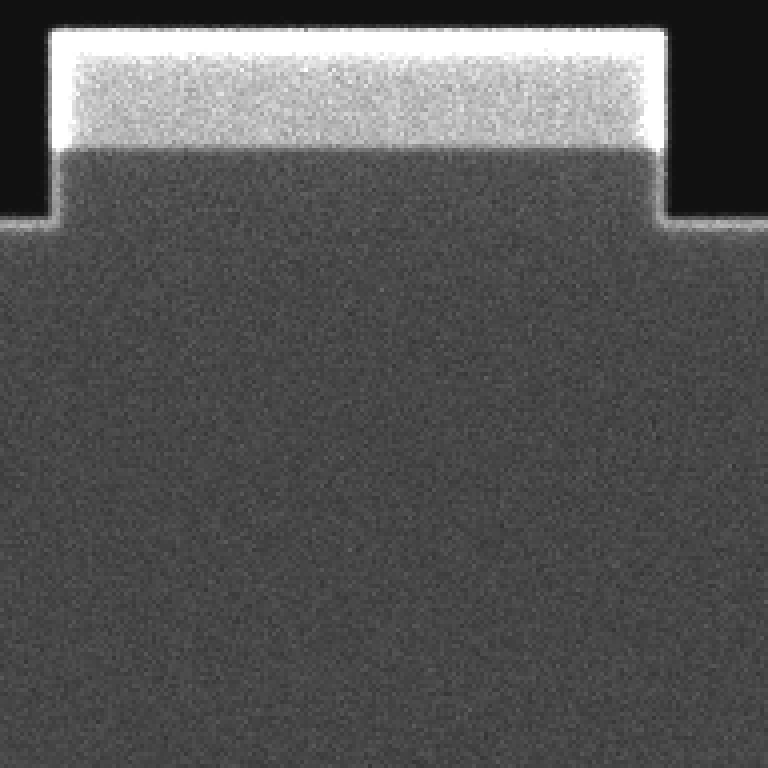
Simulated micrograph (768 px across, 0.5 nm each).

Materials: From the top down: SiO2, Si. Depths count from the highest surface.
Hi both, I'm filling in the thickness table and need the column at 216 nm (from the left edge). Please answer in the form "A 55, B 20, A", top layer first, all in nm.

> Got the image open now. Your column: SiO2 58, Si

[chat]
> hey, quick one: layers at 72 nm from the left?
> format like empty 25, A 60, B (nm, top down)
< SiO2 58, Si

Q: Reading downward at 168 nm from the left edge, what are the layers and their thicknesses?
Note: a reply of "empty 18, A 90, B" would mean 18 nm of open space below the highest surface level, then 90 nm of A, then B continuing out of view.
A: SiO2 58, Si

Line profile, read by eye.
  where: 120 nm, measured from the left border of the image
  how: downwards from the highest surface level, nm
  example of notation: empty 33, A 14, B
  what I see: SiO2 58, Si